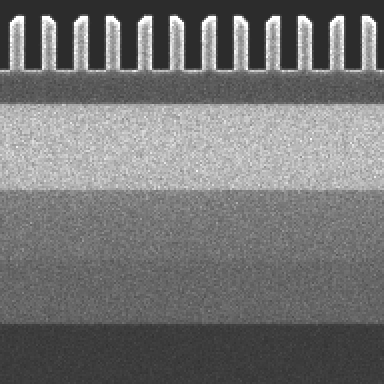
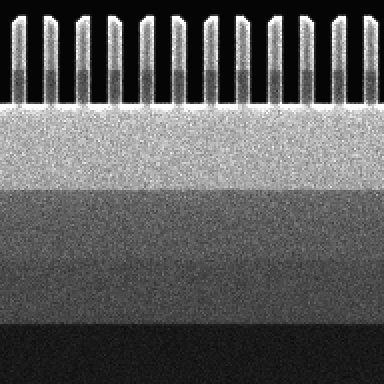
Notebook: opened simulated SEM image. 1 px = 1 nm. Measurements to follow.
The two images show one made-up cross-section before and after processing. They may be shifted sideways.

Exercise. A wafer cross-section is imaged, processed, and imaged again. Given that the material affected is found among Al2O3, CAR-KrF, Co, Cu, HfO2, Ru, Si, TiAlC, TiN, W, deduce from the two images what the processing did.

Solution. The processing removed TiN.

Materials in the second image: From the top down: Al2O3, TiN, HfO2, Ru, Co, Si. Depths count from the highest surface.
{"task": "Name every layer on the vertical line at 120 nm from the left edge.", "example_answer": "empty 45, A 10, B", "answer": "empty 6, Al2O3 48, TiN 34, HfO2 86, Ru 70, Co 64, Si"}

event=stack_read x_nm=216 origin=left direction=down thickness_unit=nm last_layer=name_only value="Al2O3 54, TiN 34, HfO2 86, Ru 70, Co 64, Si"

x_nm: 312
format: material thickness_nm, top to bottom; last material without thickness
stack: empty 6, Al2O3 48, TiN 34, HfO2 86, Ru 70, Co 64, Si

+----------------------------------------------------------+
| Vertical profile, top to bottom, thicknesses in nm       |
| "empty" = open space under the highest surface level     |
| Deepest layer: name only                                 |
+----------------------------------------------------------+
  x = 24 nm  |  Al2O3 54, TiN 34, HfO2 86, Ru 70, Co 64, Si